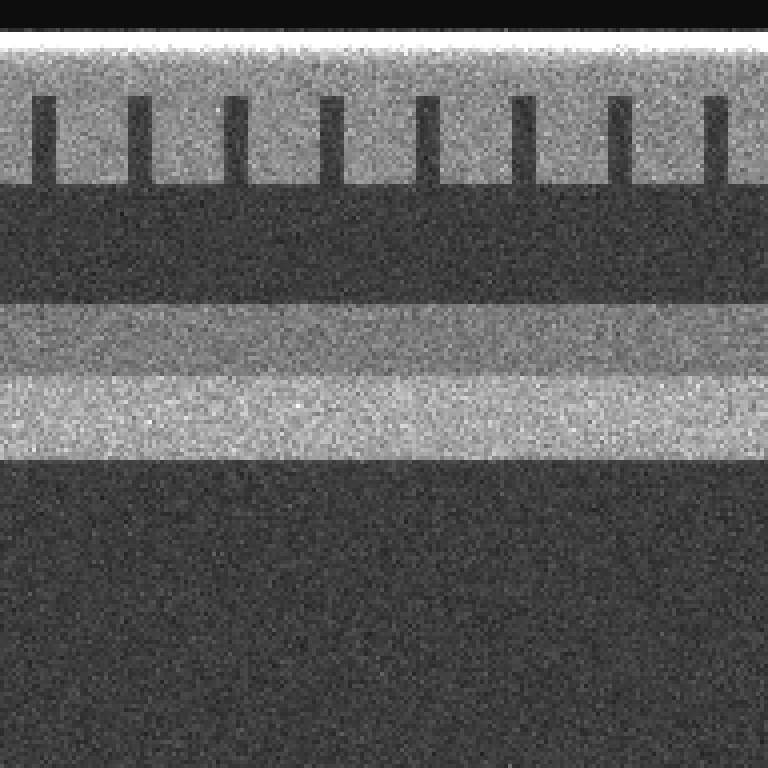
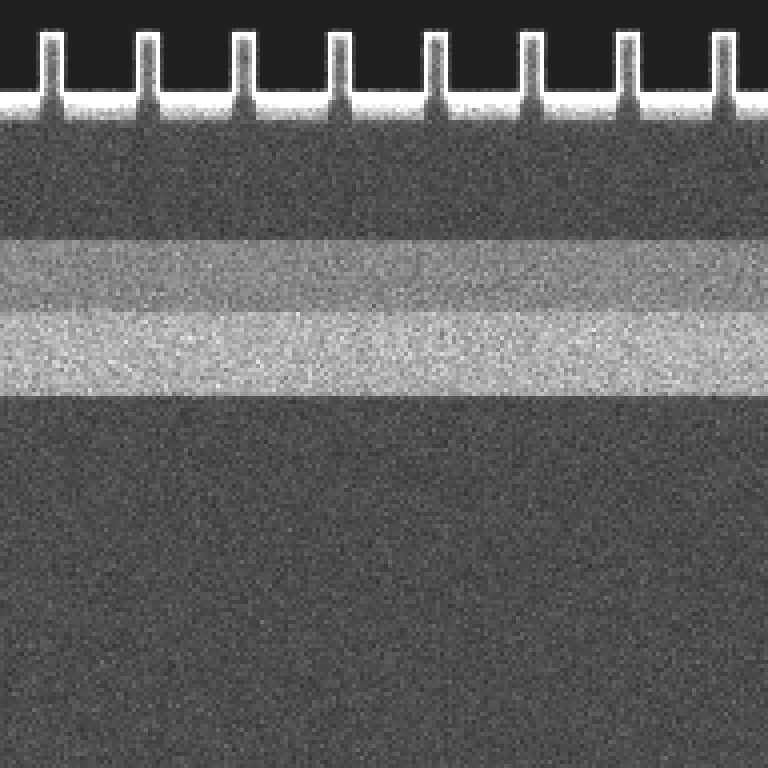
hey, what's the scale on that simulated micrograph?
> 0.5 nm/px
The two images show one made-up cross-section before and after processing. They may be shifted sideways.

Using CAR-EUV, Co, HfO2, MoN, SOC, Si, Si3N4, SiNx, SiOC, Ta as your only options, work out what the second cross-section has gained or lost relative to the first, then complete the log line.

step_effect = removed SOC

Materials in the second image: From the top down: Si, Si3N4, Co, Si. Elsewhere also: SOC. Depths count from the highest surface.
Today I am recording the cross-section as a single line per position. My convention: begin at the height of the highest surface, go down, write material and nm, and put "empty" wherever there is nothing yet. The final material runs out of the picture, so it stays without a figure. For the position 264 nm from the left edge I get Si 104, Si3N4 36, Co 42, Si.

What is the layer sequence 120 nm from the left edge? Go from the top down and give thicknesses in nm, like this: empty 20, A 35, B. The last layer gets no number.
Si 104, Si3N4 36, Co 42, Si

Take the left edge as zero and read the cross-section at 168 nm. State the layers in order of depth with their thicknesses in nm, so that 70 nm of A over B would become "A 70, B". Si 104, Si3N4 36, Co 42, Si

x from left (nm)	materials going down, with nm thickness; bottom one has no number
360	Si 104, Si3N4 36, Co 42, Si